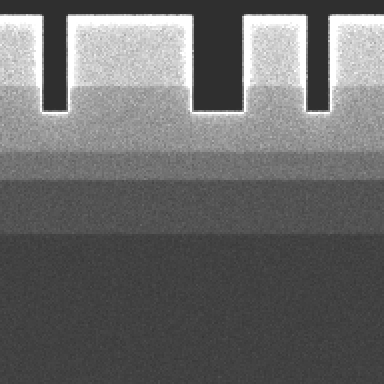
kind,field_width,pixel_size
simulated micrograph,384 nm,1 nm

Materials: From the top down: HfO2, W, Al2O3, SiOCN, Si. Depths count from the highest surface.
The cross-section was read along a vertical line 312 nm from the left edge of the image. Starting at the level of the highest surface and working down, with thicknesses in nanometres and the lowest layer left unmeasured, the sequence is empty 96, W 40, Al2O3 28, SiOCN 54, Si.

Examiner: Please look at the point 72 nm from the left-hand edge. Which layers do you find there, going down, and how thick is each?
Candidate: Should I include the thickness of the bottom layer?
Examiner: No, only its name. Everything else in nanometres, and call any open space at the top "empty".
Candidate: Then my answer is HfO2 70, W 66, Al2O3 28, SiOCN 54, Si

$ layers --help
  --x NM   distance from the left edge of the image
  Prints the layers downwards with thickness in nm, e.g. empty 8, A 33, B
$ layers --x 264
HfO2 70, W 66, Al2O3 28, SiOCN 54, Si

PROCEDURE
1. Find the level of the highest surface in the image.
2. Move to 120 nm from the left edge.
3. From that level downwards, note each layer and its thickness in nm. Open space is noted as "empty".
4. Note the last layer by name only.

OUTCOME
HfO2 70, W 66, Al2O3 28, SiOCN 54, Si